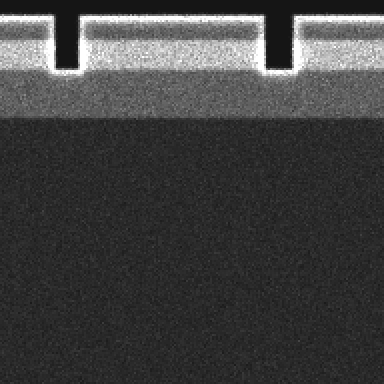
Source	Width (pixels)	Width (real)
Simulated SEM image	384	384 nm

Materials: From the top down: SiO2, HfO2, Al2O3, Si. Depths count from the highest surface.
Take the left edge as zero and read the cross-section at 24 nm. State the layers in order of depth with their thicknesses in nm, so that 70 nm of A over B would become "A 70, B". SiO2 24, HfO2 30, Al2O3 48, Si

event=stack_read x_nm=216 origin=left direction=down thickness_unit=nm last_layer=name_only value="SiO2 24, HfO2 30, Al2O3 48, Si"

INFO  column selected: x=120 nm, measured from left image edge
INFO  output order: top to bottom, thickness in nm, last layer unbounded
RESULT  SiO2 24, HfO2 30, Al2O3 48, Si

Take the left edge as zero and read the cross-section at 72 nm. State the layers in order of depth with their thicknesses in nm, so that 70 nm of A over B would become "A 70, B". empty 54, Al2O3 48, Si